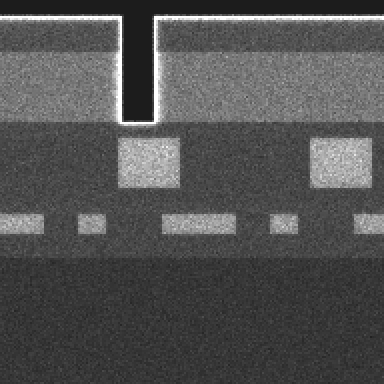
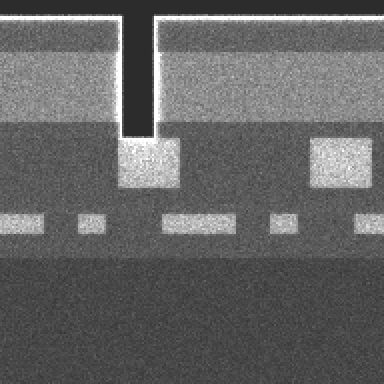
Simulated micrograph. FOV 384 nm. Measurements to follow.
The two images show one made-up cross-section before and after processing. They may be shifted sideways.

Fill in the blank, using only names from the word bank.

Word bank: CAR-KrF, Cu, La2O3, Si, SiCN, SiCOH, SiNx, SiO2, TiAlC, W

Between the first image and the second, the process removed SiCN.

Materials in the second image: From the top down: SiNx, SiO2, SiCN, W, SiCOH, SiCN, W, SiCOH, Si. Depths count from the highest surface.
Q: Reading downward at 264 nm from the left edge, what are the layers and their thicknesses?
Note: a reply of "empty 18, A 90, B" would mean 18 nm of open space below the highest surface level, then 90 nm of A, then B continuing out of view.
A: SiNx 36, SiO2 70, SiCN 16, SiCOH 66, SiCN 10, SiCOH 44, Si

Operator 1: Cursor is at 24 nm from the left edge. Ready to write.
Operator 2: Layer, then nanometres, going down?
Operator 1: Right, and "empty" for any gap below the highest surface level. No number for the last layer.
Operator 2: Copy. SiNx 36, SiO2 70, SiCN 16, SiCOH 66, SiCN 10, W 20, SiCOH 24, Si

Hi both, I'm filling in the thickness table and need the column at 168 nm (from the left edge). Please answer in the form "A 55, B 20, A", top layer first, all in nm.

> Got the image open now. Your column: SiNx 36, SiO2 70, SiCN 16, W 50, SiCOH 16, SiCN 10, W 20, SiCOH 24, Si